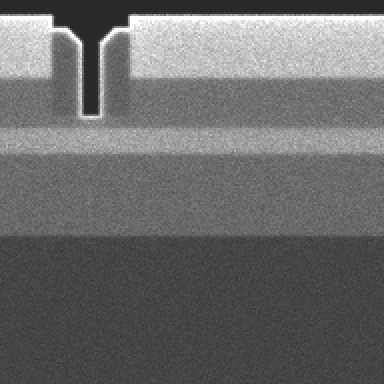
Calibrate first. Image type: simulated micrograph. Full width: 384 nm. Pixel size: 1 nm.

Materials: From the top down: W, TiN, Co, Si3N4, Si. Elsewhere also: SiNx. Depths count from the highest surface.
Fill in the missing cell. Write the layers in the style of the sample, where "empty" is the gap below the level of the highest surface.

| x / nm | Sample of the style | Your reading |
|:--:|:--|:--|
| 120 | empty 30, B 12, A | empty 12, SiNx 88, TiN 12, Co 26, Si3N4 82, Si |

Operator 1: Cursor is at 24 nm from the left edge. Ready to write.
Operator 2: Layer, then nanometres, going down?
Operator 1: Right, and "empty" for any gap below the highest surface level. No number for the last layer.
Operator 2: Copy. W 62, TiN 50, Co 26, Si3N4 82, Si